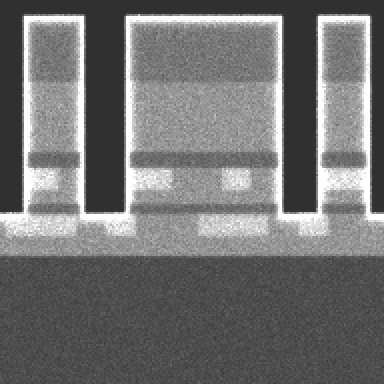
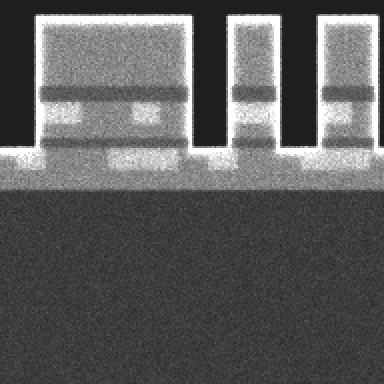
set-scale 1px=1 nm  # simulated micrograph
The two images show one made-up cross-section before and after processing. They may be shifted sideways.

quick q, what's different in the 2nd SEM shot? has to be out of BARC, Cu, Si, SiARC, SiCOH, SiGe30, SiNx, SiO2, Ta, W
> SiARC removed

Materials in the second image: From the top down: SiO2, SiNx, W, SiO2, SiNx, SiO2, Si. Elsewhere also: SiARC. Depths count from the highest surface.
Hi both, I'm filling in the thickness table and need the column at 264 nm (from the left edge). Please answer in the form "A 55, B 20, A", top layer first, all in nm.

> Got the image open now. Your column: SiO2 70, SiNx 16, W 22, SiO2 14, SiNx 10, SiO2 42, Si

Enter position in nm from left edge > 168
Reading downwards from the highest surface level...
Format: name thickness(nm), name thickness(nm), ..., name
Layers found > SiO2 70, SiNx 16, SiO2 36, SiNx 10, W 22, SiO2 20, Si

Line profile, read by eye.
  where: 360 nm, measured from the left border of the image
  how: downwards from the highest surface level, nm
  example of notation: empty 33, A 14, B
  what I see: SiO2 70, SiNx 16, SiO2 36, SiNx 10, W 22, SiO2 20, Si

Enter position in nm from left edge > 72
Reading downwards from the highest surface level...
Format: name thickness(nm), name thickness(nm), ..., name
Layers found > SiO2 70, SiNx 16, W 22, SiO2 14, SiNx 10, SiO2 42, Si